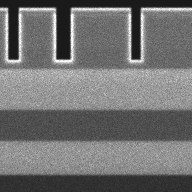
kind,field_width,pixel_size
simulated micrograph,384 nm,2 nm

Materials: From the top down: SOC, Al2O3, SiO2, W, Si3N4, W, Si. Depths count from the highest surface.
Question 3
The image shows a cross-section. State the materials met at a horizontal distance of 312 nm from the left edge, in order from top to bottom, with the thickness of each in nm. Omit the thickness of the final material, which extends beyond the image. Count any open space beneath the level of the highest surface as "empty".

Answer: SOC 12, Al2O3 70, SiO2 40, W 82, Si3N4 62, W 68, Si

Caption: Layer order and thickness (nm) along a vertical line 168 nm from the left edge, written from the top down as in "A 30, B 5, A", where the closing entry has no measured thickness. SOC 12, Al2O3 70, SiO2 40, W 82, Si3N4 62, W 68, Si